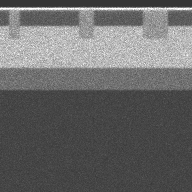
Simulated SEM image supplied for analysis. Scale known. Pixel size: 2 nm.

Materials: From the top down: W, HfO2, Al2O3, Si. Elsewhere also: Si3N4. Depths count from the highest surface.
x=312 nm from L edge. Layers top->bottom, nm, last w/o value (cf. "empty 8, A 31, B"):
W 62, HfO2 58, Al2O3 44, Si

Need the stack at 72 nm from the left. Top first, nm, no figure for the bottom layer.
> Si3N4 36, HfO2 84, Al2O3 44, Si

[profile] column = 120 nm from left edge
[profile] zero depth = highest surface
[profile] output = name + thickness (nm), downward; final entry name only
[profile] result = Si3N4 36, HfO2 84, Al2O3 44, Si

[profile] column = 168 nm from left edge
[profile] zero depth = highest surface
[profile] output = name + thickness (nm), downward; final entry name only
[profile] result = W 62, HfO2 58, Al2O3 44, Si